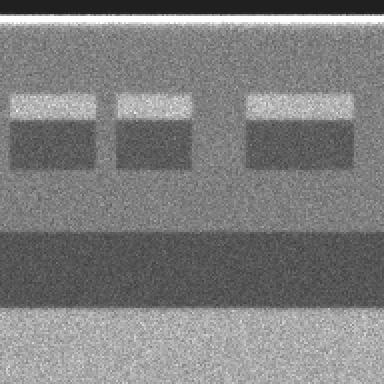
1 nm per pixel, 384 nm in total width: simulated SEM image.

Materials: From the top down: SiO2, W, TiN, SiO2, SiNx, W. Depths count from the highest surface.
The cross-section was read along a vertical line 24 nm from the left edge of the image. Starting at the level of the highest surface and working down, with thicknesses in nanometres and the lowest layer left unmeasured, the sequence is SiO2 78, W 26, TiN 50, SiO2 62, SiNx 76, W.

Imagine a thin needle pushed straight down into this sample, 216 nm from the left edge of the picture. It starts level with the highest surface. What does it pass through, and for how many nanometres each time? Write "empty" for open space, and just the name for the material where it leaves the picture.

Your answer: SiO2 216, SiNx 76, W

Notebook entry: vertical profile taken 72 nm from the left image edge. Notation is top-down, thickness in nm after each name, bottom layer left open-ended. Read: SiO2 78, W 26, TiN 50, SiO2 62, SiNx 76, W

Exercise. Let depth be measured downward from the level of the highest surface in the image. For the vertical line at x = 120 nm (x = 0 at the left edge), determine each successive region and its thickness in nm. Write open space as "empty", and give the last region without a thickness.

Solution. SiO2 78, W 26, TiN 50, SiO2 62, SiNx 76, W